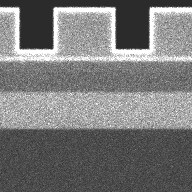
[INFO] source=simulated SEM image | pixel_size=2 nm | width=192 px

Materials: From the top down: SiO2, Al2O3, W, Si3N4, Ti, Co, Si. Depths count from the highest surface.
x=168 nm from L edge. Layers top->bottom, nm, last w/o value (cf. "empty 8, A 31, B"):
SiO2 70, Al2O3 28, W 8, Si3N4 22, Ti 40, Co 74, Si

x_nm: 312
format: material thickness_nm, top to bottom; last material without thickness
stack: SiO2 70, Al2O3 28, W 8, Si3N4 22, Ti 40, Co 74, Si